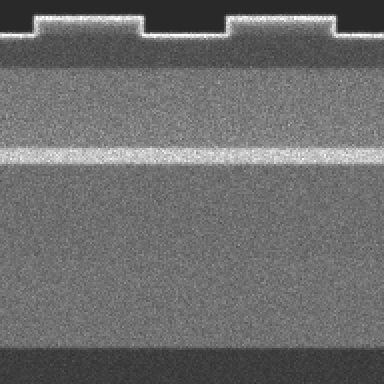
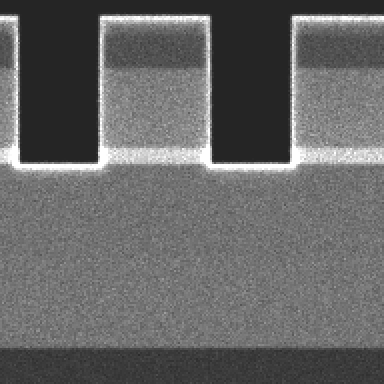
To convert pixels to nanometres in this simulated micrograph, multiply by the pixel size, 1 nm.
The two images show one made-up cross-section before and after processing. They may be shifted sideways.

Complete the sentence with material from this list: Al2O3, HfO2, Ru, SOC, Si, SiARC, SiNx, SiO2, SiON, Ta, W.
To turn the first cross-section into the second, HfO2 and Ru and SiNx must be removed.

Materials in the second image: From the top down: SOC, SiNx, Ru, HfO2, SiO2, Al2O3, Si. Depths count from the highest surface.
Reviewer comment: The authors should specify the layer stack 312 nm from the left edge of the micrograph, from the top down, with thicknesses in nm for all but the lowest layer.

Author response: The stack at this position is SOC 18, SiNx 34, Ru 80, HfO2 16, SiO2 94, Al2O3 90, Si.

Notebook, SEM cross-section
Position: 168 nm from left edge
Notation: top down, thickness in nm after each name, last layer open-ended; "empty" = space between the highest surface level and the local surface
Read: SOC 18, SiNx 34, Ru 80, HfO2 16, SiO2 94, Al2O3 90, Si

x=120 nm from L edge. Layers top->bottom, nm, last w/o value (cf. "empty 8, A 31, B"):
SOC 18, SiNx 34, Ru 80, HfO2 16, SiO2 94, Al2O3 90, Si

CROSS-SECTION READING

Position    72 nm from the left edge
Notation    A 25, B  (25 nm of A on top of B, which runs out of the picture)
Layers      empty 148, SiO2 94, Al2O3 90, Si